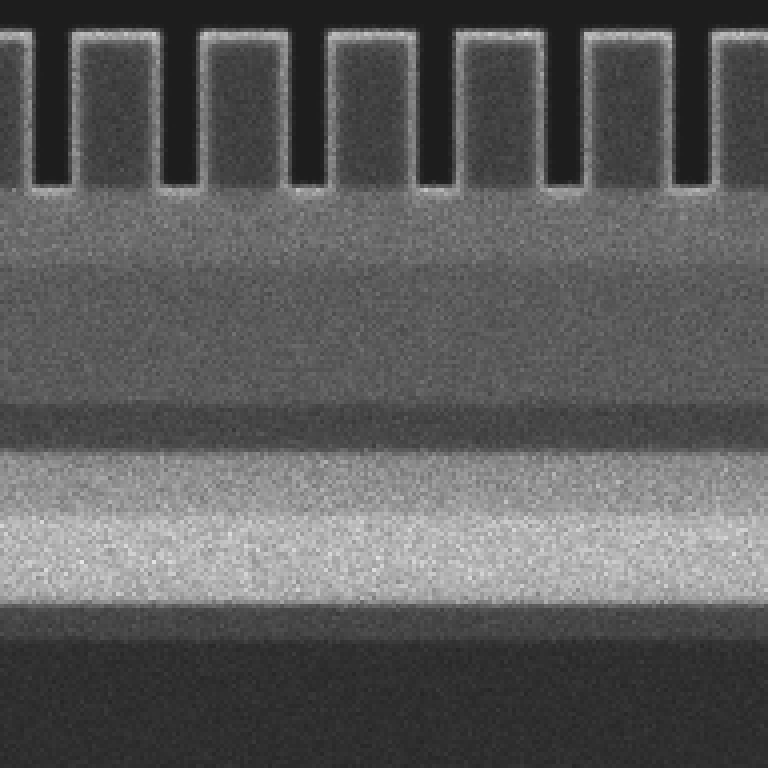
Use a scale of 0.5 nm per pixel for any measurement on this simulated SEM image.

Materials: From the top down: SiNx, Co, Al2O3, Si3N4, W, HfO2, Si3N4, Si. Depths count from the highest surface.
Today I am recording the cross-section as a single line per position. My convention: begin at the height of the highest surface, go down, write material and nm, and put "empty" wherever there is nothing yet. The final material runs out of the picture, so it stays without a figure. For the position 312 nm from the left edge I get SiNx 78, Co 38, Al2O3 70, Si3N4 24, W 32, HfO2 44, Si3N4 18, Si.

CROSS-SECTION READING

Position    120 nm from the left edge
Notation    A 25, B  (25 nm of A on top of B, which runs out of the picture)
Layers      SiNx 78, Co 38, Al2O3 70, Si3N4 24, W 32, HfO2 44, Si3N4 18, Si